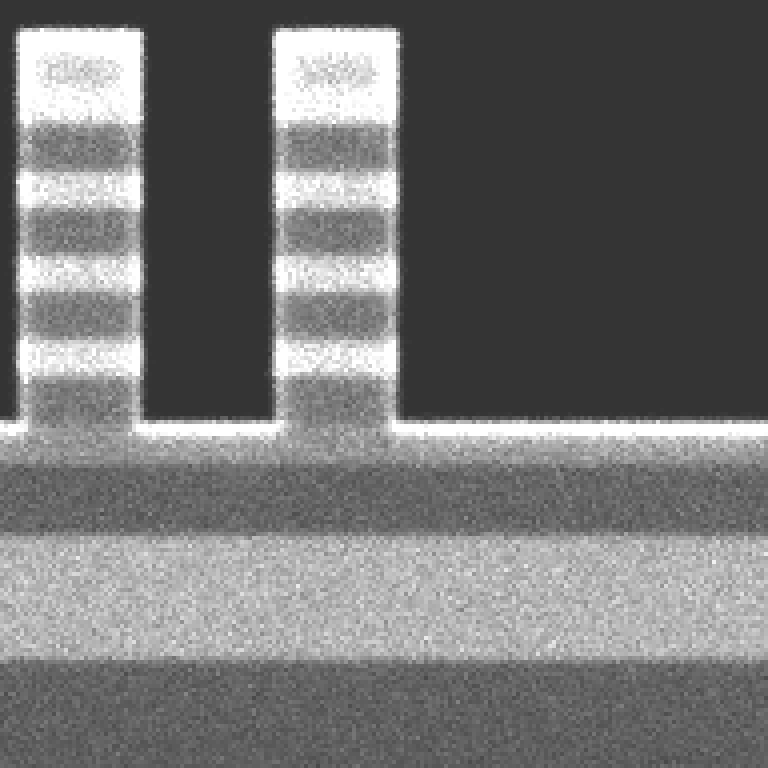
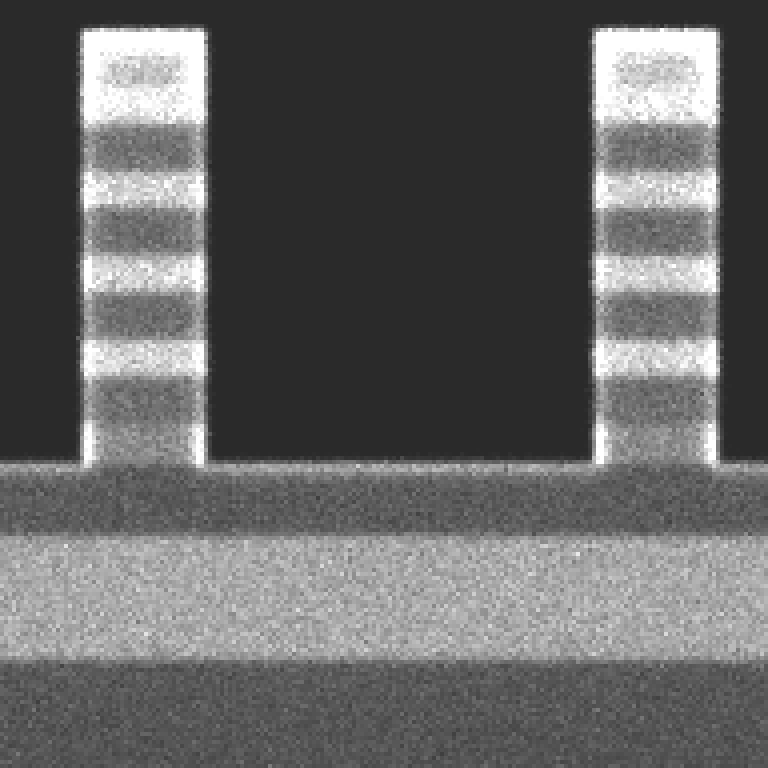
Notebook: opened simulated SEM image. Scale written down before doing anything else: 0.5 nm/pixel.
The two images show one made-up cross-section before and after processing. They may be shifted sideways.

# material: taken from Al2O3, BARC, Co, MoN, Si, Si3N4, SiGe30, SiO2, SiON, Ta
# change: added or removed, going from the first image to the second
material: Si3N4
change: removed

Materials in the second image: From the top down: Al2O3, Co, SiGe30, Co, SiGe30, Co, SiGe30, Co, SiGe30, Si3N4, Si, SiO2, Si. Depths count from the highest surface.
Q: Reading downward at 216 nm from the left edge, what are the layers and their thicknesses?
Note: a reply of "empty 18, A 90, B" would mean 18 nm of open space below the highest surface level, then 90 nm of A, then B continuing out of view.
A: empty 216, Si 36, SiO2 62, Si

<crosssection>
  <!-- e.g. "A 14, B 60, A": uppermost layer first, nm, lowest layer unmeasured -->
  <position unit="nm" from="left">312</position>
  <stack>Al2O3 28, Co 18, SiGe30 24, Co 18, SiGe30 24, Co 18, SiGe30 24, Co 18, SiGe30 24, Si3N4 20, Si 36, SiO2 62, Si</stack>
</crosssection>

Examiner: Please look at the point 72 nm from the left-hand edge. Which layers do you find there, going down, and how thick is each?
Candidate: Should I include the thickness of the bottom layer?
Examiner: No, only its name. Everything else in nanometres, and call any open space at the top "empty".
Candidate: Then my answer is Al2O3 28, Co 18, SiGe30 24, Co 18, SiGe30 24, Co 18, SiGe30 24, Co 18, SiGe30 24, Si3N4 20, Si 36, SiO2 62, Si